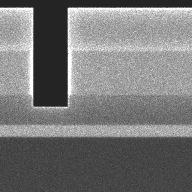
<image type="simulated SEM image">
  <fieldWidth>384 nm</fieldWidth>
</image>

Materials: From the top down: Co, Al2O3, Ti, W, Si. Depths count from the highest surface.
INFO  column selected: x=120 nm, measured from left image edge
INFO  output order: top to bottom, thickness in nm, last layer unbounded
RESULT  empty 198, Ti 36, W 24, Si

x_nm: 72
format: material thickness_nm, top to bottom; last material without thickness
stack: empty 198, Ti 36, W 24, Si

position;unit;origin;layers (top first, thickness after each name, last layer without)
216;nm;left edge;Co 86, Al2O3 88, Ti 60, W 24, Si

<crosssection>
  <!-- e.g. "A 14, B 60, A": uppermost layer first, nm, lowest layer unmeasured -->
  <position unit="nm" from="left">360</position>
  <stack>Co 86, Al2O3 88, Ti 60, W 24, Si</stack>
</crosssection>